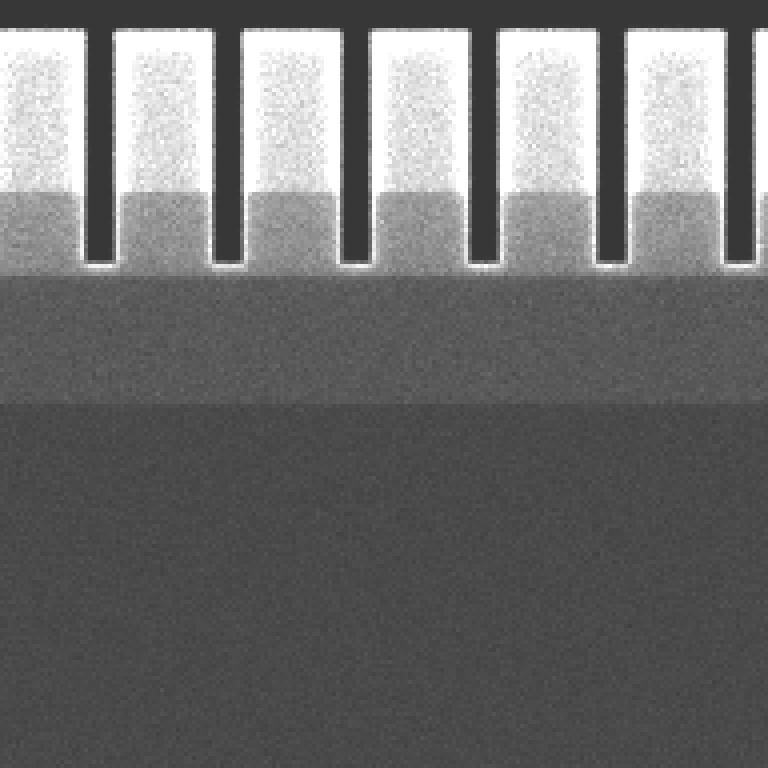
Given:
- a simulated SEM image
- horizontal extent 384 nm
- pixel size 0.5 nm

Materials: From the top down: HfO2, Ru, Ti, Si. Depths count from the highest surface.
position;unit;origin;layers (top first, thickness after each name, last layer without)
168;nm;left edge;HfO2 80, Ru 42, Ti 64, Si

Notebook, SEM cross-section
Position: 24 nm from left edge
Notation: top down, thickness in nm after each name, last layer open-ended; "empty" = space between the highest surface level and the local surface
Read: HfO2 80, Ru 42, Ti 64, Si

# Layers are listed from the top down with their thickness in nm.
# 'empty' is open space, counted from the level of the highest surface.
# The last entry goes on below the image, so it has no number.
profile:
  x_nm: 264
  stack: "HfO2 80, Ru 42, Ti 64, Si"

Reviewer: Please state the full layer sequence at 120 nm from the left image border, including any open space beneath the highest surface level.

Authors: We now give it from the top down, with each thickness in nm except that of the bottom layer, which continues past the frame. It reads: empty 116, Ru 6, Ti 64, Si